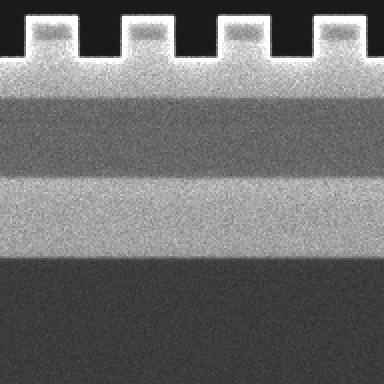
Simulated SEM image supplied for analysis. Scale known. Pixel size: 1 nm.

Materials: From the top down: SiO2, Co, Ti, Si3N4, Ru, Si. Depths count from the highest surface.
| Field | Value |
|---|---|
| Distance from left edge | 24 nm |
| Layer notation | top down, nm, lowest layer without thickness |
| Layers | empty 42, Co 40, Ti 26, Si3N4 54, Ru 80, Si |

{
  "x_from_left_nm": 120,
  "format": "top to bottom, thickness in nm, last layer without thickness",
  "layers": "empty 42, Co 40, Ti 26, Si3N4 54, Ru 80, Si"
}